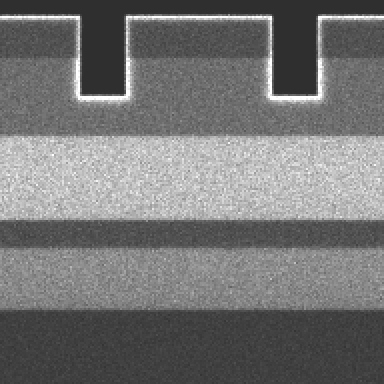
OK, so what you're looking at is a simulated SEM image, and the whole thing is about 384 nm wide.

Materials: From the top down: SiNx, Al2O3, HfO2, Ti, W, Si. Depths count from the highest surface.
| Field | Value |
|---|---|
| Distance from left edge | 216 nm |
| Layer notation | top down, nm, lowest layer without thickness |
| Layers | SiNx 42, Al2O3 78, HfO2 84, Ti 28, W 62, Si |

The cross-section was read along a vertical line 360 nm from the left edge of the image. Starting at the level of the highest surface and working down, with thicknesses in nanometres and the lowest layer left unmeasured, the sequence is SiNx 42, Al2O3 78, HfO2 84, Ti 28, W 62, Si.